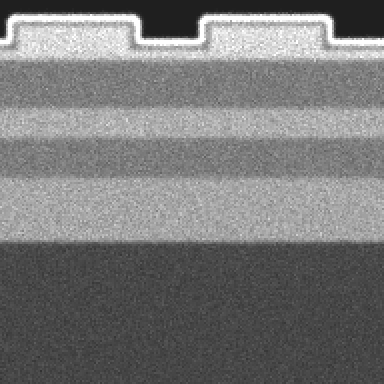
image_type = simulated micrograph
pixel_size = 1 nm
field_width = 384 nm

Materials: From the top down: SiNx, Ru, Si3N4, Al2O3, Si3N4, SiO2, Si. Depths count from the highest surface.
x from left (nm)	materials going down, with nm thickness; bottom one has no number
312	SiNx 10, Ru 34, Si3N4 48, Al2O3 30, Si3N4 40, SiO2 64, Si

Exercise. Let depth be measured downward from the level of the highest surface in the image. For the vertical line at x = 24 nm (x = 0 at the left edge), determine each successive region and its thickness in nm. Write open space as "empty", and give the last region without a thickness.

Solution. SiNx 10, Ru 34, Si3N4 48, Al2O3 30, Si3N4 40, SiO2 64, Si